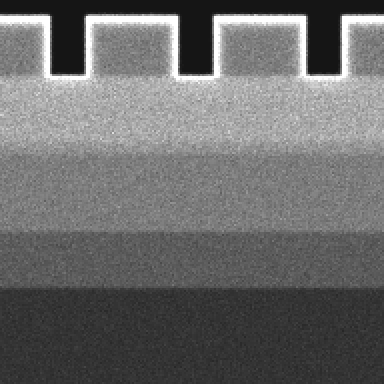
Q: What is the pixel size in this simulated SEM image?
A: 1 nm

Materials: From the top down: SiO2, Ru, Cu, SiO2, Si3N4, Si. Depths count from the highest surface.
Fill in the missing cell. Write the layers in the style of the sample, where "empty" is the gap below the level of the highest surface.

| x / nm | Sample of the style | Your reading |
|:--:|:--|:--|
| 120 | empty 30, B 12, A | SiO2 60, Ru 66, Cu 12, SiO2 78, Si3N4 56, Si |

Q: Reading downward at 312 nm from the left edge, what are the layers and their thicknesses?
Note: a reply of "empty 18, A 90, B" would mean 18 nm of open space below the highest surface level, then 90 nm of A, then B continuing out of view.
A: empty 60, Ru 66, Cu 12, SiO2 78, Si3N4 56, Si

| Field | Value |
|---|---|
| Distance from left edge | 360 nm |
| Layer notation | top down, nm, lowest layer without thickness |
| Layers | SiO2 60, Ru 66, Cu 12, SiO2 78, Si3N4 56, Si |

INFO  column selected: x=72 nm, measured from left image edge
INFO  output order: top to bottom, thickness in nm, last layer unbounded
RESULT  empty 60, Ru 66, Cu 12, SiO2 78, Si3N4 56, Si